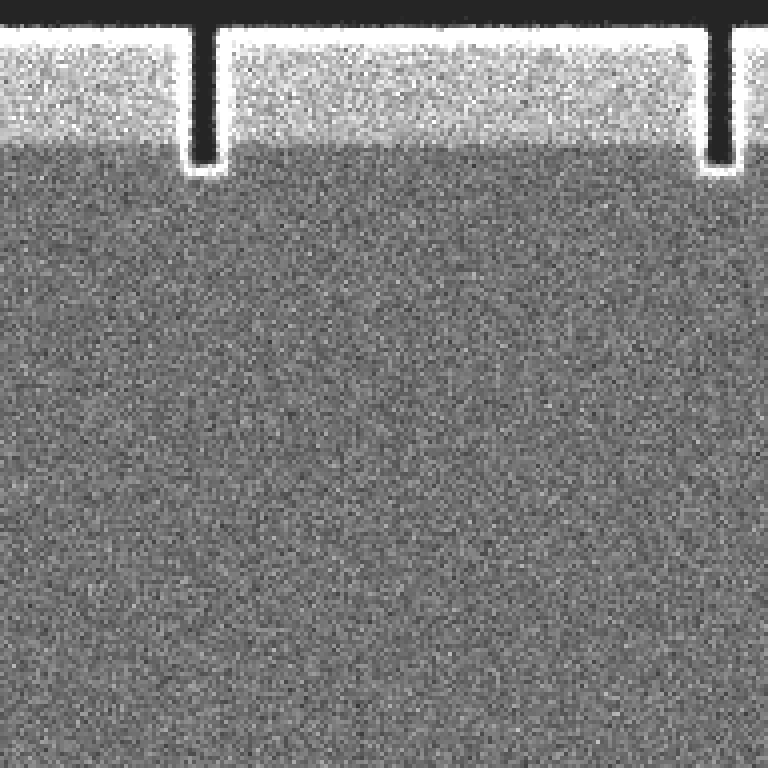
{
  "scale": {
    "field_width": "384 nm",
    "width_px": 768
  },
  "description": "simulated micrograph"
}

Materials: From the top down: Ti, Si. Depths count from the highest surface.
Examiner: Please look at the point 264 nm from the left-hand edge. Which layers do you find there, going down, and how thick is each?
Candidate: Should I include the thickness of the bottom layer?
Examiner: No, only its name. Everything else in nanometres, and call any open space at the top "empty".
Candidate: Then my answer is Ti 56, Si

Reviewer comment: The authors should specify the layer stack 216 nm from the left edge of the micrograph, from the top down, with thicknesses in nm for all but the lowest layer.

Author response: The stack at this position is Ti 56, Si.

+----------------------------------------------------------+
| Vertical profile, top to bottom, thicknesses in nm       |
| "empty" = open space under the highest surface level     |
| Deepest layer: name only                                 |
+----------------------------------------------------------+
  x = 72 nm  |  Ti 56, Si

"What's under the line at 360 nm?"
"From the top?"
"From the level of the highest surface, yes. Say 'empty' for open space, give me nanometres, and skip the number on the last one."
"empty 68, Si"